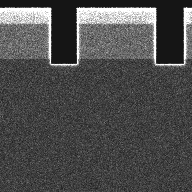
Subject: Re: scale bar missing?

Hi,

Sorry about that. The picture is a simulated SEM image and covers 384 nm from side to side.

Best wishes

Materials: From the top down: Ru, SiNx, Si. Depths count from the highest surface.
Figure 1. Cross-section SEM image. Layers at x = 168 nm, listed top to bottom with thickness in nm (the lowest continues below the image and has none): Ru 32, SiNx 70, Si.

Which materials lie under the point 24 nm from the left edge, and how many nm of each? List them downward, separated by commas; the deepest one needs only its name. Ru 32, SiNx 70, Si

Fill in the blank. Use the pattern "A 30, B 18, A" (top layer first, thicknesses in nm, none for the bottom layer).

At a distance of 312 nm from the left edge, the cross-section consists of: empty 112, Si